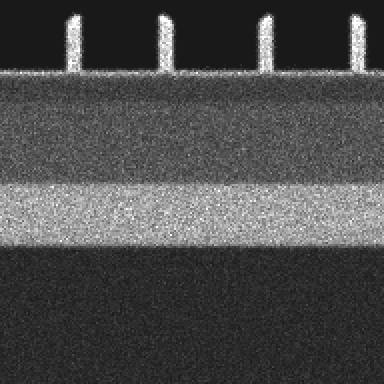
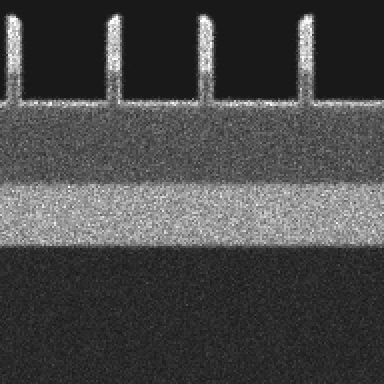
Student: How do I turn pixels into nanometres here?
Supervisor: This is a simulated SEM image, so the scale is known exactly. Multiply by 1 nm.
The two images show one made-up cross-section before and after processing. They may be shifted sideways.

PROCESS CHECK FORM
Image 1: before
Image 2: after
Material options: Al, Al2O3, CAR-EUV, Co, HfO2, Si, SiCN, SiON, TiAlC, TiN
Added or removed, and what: removed, TiN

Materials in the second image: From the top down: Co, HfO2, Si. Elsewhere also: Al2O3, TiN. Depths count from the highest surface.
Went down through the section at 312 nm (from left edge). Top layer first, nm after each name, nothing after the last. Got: empty 86, Co 82, HfO2 62, Si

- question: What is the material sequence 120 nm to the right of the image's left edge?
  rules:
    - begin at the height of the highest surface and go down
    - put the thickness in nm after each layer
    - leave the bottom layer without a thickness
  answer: empty 86, Co 82, HfO2 62, Si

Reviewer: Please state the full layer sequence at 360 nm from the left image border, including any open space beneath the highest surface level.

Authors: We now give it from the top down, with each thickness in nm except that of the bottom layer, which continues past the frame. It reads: empty 86, Co 82, HfO2 62, Si